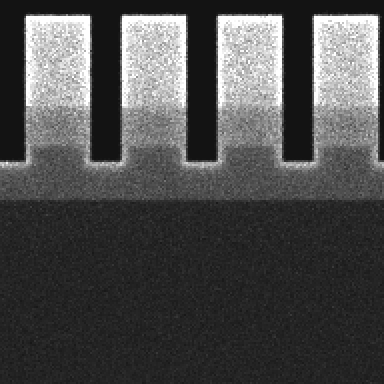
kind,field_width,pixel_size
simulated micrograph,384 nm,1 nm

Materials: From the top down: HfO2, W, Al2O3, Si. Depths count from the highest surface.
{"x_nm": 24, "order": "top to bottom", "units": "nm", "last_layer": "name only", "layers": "empty 146, Al2O3 38, Si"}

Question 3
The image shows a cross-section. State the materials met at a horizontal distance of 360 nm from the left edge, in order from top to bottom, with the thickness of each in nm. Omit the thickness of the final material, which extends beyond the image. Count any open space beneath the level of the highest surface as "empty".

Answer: HfO2 90, W 40, Al2O3 54, Si